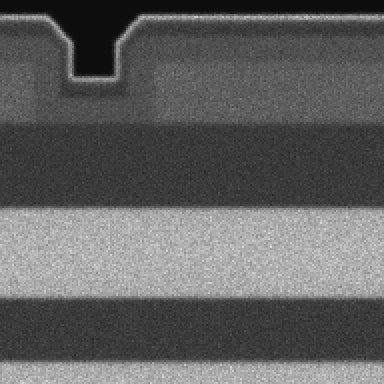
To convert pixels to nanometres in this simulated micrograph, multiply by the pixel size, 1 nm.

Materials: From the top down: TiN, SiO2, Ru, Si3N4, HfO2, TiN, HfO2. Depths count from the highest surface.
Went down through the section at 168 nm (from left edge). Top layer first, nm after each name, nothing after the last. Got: TiN 20, SiO2 26, Ru 62, Si3N4 84, HfO2 90, TiN 64, HfO2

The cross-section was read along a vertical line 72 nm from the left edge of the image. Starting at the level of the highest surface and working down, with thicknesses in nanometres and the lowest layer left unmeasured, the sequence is empty 62, TiN 20, SiO2 26, Si3N4 84, HfO2 90, TiN 64, HfO2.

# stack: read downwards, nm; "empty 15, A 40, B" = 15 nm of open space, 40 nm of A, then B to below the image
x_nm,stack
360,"TiN 20, SiO2 26, Ru 62, Si3N4 84, HfO2 90, TiN 64, HfO2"